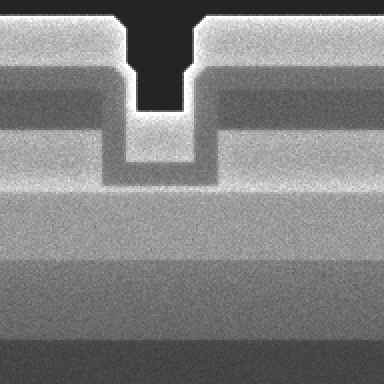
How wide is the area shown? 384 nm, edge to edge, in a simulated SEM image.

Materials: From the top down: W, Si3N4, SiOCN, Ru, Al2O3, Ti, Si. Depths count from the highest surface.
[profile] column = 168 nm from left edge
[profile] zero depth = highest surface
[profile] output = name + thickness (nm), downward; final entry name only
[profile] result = empty 96, W 50, Si3N4 24, Ru 6, Al2O3 68, Ti 80, Si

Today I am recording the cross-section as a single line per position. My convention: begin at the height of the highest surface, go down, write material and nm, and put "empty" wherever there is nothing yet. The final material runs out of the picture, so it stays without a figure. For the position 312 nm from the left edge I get W 50, Si3N4 24, SiOCN 40, Ru 62, Al2O3 68, Ti 80, Si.